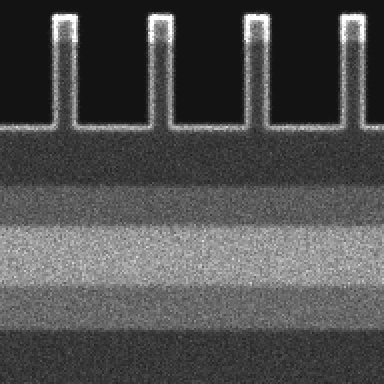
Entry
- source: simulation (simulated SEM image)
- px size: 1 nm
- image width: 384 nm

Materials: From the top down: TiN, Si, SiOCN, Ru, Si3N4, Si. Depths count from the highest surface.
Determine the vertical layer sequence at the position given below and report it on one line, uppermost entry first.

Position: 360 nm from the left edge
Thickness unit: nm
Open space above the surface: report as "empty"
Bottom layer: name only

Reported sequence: TiN 26, Si 144, SiOCN 40, Ru 60, Si3N4 44, Si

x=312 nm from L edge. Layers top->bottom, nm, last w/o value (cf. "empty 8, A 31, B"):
empty 110, Si 60, SiOCN 40, Ru 60, Si3N4 44, Si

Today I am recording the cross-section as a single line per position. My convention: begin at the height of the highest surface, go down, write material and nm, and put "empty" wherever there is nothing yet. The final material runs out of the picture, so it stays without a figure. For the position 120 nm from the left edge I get empty 110, Si 60, SiOCN 40, Ru 60, Si3N4 44, Si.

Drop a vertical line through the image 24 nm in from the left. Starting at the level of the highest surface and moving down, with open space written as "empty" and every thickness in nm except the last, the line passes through empty 110, Si 60, SiOCN 40, Ru 60, Si3N4 44, Si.